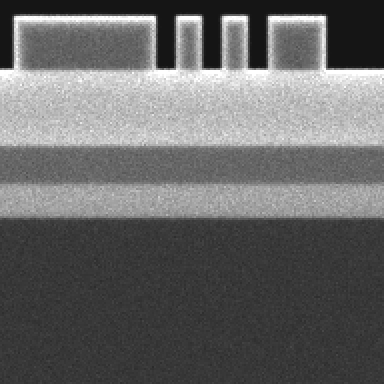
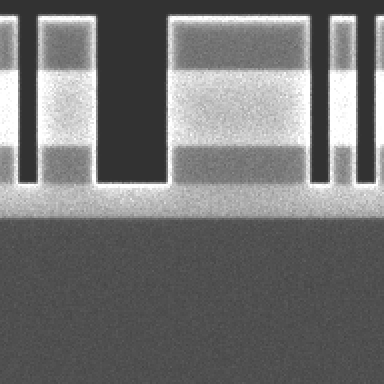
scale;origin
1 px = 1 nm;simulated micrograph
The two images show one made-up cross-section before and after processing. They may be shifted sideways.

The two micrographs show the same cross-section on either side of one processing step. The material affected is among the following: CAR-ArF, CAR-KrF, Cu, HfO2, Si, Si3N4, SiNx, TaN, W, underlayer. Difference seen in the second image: Si3N4 and W removed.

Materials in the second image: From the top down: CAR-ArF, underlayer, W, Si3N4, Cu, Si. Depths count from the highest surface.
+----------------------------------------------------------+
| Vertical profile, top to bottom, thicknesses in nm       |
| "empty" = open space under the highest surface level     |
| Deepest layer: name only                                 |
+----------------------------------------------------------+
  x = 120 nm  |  empty 168, Cu 34, Si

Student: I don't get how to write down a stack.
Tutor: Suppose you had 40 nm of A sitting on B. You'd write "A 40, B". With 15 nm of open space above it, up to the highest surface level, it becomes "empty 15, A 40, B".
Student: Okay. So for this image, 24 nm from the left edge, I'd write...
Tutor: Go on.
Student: empty 168, Cu 34, Si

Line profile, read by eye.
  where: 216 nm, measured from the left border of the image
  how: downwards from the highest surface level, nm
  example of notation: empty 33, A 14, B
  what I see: CAR-ArF 32, underlayer 22, W 76, Si3N4 38, Cu 34, Si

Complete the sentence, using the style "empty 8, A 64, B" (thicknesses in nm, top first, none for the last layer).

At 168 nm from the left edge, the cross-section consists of CAR-ArF 32, underlayer 22, W 76, Si3N4 38, Cu 34, Si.